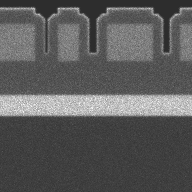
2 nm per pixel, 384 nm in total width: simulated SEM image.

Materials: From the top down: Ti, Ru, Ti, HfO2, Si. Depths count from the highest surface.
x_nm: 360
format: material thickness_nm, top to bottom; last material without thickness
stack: Ti 32, Ru 74, Ti 68, HfO2 42, Si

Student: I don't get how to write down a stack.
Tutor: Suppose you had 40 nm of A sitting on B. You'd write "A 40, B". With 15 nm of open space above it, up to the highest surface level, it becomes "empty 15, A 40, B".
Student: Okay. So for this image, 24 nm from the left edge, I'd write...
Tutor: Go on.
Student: Ti 32, Ru 74, Ti 68, HfO2 42, Si